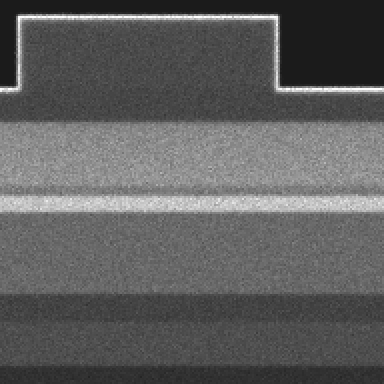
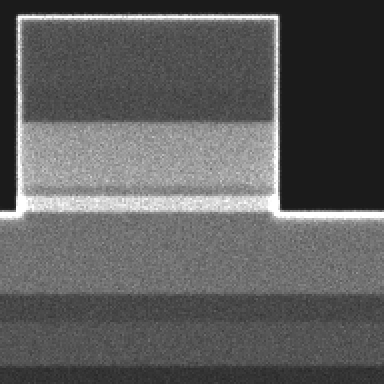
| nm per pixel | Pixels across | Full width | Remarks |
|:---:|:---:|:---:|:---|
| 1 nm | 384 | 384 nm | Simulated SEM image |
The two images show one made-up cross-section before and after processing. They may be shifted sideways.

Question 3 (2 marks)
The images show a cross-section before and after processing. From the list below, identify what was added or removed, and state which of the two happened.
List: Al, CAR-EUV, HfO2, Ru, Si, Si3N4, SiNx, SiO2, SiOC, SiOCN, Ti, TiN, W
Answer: HfO2 and Ru and SiNx and W was removed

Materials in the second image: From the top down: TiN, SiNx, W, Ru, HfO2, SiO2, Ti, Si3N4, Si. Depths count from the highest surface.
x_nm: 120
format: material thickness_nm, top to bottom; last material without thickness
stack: TiN 72, SiNx 34, W 64, Ru 10, HfO2 16, SiO2 82, Ti 28, Si3N4 44, Si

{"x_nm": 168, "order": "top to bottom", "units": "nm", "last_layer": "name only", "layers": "TiN 72, SiNx 34, W 64, Ru 10, HfO2 16, SiO2 82, Ti 28, Si3N4 44, Si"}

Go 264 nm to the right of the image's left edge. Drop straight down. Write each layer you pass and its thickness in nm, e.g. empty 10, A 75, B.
TiN 72, SiNx 34, W 64, Ru 10, HfO2 16, SiO2 82, Ti 28, Si3N4 44, Si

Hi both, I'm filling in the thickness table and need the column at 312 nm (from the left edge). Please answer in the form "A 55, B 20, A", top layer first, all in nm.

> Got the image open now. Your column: empty 196, SiO2 82, Ti 28, Si3N4 44, Si